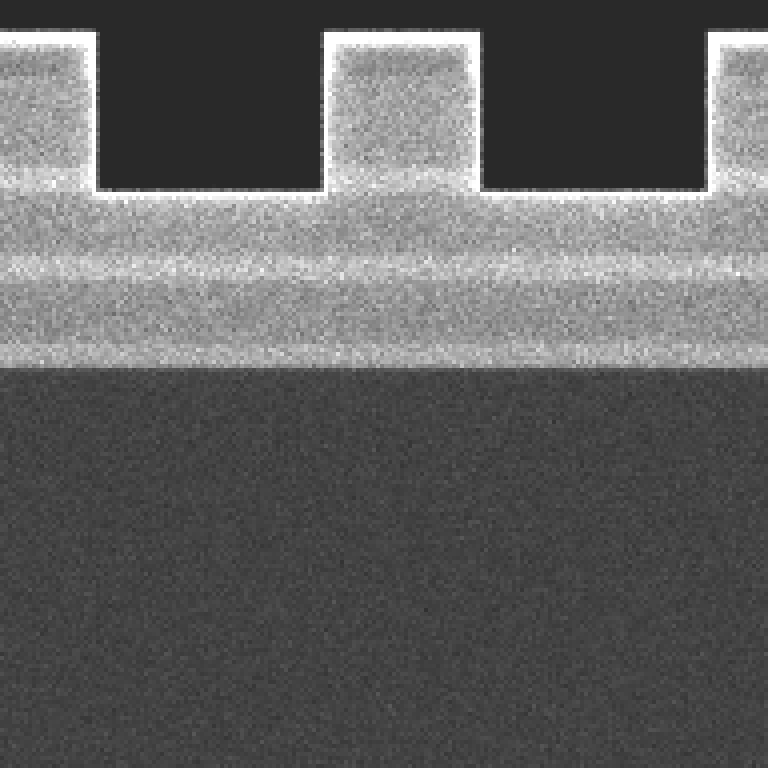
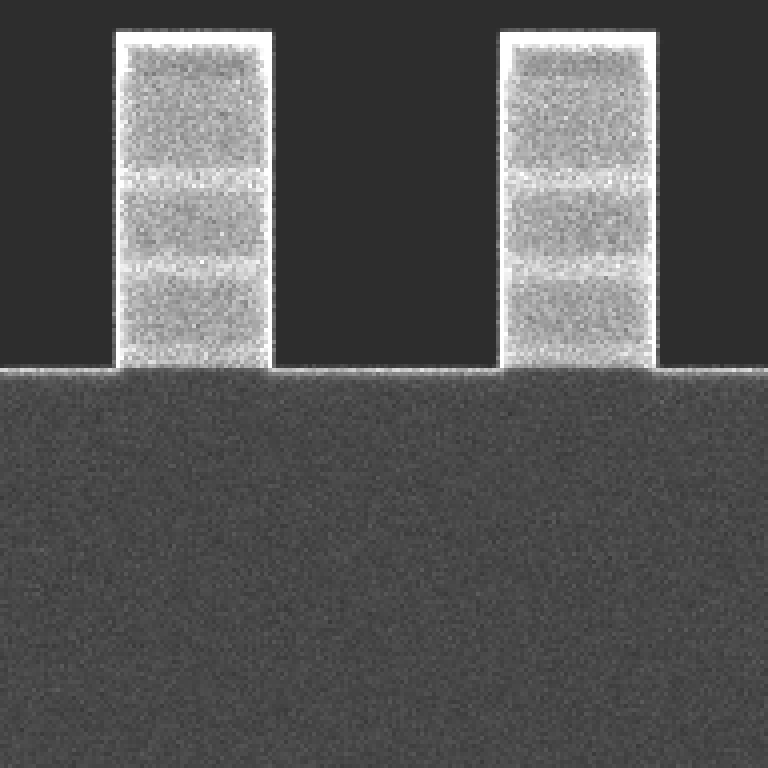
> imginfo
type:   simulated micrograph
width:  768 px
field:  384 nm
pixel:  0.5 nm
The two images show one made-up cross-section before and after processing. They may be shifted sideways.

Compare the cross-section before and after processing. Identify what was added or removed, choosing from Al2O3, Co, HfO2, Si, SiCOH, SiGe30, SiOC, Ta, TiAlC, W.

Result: Co and W removed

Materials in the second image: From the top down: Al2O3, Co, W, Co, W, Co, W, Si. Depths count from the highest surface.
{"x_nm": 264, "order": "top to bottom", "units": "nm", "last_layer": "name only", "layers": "Al2O3 22, Co 46, W 12, Co 32, W 12, Co 32, W 12, Si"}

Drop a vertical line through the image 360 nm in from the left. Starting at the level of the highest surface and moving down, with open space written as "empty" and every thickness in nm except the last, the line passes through empty 168, Si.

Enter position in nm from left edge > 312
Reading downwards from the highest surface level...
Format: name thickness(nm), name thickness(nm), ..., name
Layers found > Al2O3 22, Co 46, W 12, Co 32, W 12, Co 32, W 12, Si